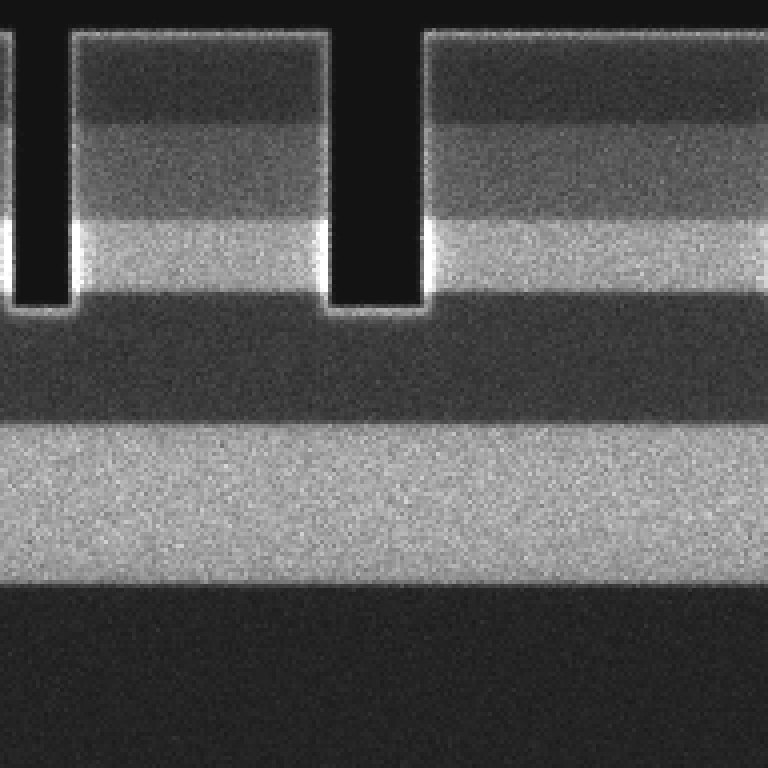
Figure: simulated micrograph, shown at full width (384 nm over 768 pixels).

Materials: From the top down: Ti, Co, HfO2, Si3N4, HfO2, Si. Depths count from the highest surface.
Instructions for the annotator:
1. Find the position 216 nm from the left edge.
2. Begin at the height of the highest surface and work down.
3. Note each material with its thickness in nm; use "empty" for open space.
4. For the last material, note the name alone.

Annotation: Ti 46, Co 48, HfO2 36, Si3N4 66, HfO2 80, Si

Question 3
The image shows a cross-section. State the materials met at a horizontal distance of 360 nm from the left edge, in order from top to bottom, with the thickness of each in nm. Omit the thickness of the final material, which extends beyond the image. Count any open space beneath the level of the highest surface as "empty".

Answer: Ti 46, Co 48, HfO2 36, Si3N4 66, HfO2 80, Si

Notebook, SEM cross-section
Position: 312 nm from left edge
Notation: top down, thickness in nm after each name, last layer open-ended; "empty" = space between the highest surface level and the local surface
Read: Ti 46, Co 48, HfO2 36, Si3N4 66, HfO2 80, Si